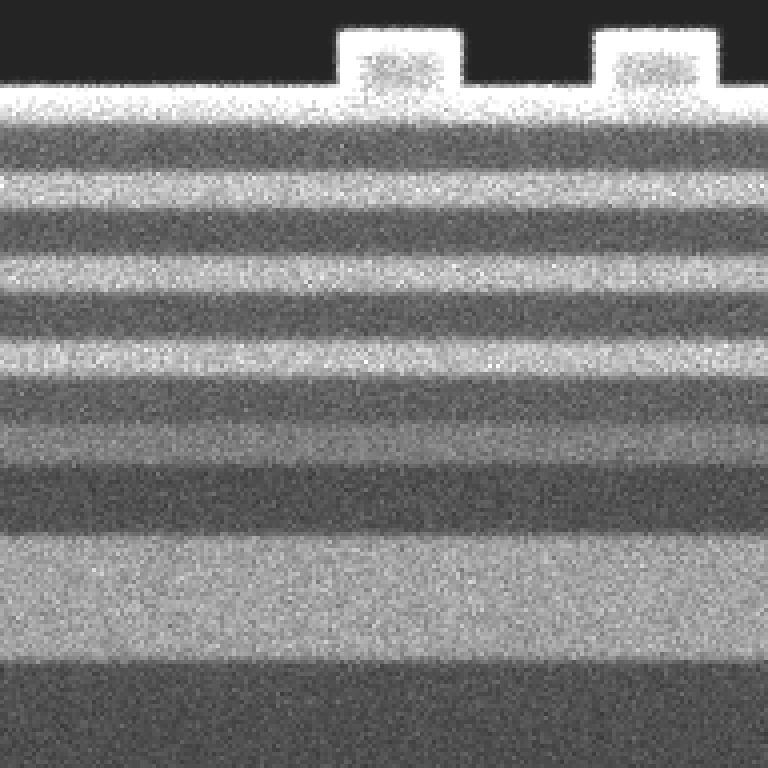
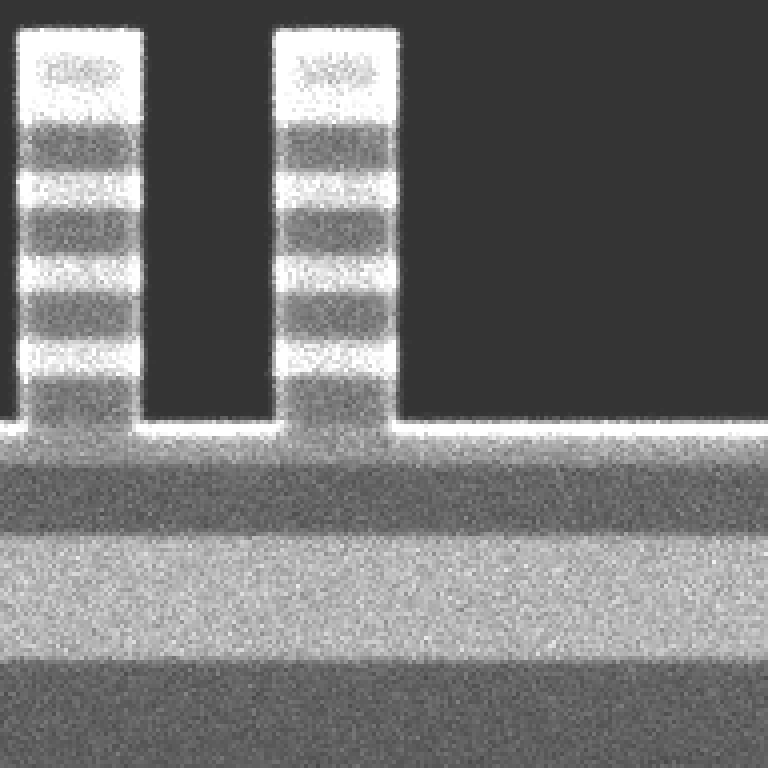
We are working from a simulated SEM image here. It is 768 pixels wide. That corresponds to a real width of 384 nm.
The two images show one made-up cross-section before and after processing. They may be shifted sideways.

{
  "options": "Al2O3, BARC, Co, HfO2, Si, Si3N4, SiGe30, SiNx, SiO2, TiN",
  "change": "removed",
  "material": "Co and SiGe30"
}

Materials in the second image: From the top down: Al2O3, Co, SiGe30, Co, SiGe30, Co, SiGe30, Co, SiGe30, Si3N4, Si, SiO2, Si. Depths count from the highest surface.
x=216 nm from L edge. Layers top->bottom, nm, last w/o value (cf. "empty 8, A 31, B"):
empty 196, Si3N4 20, Si 36, SiO2 62, Si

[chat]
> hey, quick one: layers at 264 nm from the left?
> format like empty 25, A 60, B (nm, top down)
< empty 196, Si3N4 20, Si 36, SiO2 62, Si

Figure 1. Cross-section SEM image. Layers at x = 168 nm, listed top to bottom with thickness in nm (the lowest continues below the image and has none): Al2O3 28, Co 18, SiGe30 24, Co 18, SiGe30 24, Co 18, SiGe30 24, Co 18, SiGe30 24, Si3N4 20, Si 36, SiO2 62, Si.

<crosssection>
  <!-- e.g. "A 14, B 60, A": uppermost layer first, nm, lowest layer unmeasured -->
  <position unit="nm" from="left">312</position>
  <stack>empty 196, Si3N4 20, Si 36, SiO2 62, Si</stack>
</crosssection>